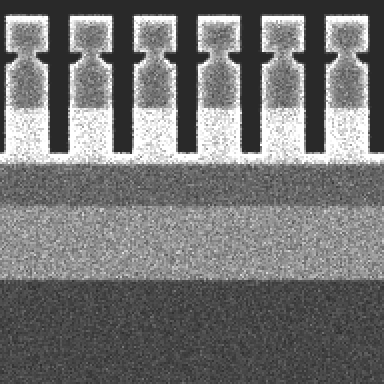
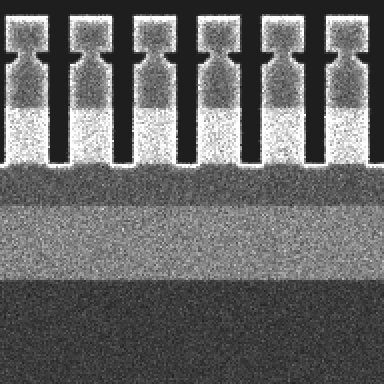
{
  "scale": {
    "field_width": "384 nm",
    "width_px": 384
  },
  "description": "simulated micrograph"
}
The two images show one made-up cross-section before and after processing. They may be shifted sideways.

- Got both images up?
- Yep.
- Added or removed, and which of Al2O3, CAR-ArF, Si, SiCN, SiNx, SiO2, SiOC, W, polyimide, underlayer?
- removed, W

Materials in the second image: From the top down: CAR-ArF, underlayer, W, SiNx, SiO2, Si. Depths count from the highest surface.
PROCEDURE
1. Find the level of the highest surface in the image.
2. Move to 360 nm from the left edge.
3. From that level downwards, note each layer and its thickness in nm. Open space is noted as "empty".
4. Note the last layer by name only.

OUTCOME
CAR-ArF 36, empty 10, underlayer 46, W 56, SiNx 42, SiO2 74, Si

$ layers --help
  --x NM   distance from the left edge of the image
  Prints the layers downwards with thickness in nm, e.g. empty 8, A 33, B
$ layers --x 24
CAR-ArF 36, underlayer 56, W 56, SiNx 42, SiO2 74, Si